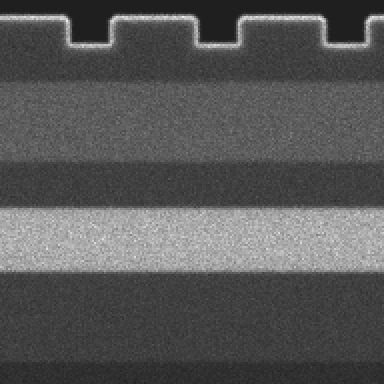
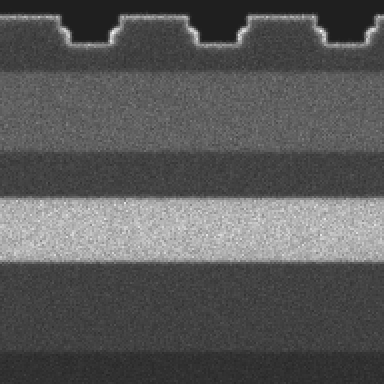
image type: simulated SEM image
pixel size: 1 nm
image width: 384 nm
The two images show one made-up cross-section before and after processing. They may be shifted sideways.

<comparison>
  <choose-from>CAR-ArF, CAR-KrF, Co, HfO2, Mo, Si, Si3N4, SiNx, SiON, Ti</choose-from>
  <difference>Si3N4 removed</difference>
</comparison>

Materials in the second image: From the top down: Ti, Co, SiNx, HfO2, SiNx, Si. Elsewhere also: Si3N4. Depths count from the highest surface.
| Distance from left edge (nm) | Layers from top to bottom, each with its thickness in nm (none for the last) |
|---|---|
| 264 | Ti 56, Co 80, SiNx 46, HfO2 64, SiNx 90, Si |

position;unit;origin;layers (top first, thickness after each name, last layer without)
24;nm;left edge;Ti 56, Co 80, SiNx 46, HfO2 64, SiNx 90, Si